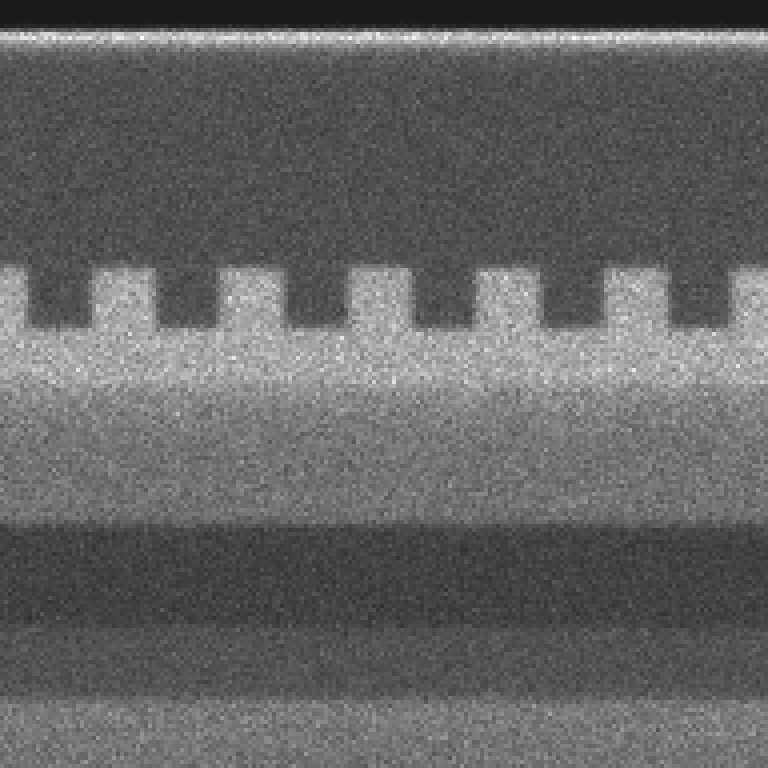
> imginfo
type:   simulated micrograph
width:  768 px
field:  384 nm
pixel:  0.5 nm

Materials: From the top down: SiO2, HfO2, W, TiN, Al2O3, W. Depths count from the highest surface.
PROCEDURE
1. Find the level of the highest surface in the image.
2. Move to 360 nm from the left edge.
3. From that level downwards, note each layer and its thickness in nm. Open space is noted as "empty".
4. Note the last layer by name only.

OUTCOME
SiO2 148, HfO2 28, W 70, TiN 52, Al2O3 36, W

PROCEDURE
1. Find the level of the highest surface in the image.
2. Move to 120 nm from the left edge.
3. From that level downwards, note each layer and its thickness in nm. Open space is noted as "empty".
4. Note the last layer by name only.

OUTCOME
SiO2 118, HfO2 58, W 70, TiN 52, Al2O3 36, W